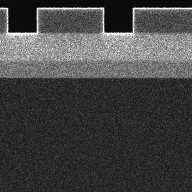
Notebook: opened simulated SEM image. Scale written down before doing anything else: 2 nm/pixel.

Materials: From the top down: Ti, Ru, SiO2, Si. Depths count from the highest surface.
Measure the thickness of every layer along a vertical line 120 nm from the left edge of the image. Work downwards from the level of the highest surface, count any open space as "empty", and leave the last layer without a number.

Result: Ti 50, Ru 56, SiO2 34, Si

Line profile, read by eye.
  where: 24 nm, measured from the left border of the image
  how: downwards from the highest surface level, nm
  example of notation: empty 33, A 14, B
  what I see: empty 50, Ru 56, SiO2 34, Si